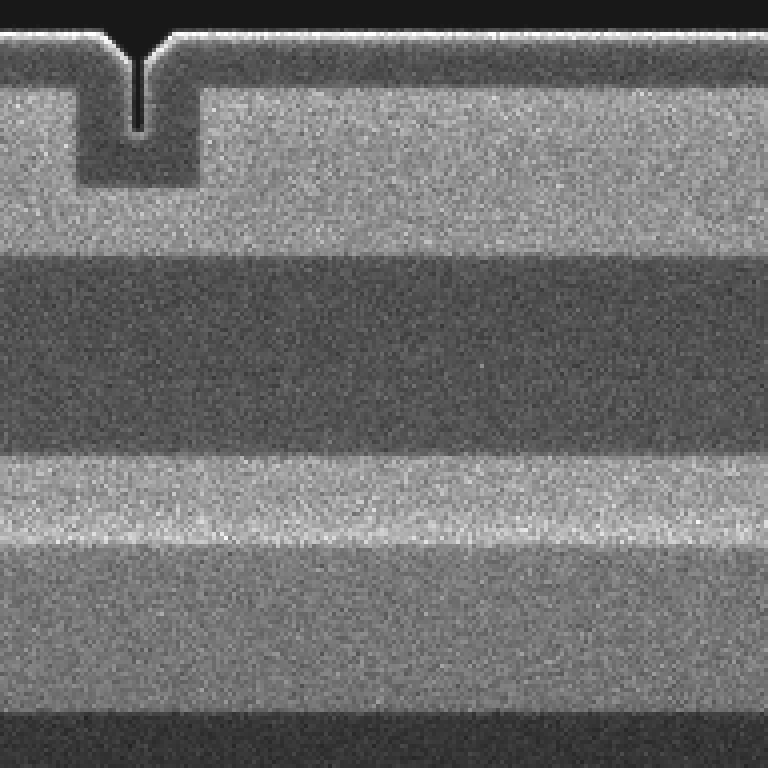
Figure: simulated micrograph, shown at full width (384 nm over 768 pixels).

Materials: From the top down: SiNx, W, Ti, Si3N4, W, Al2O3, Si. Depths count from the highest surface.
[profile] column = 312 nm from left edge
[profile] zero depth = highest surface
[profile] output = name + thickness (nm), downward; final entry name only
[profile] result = SiNx 28, W 84, Ti 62, Si3N4 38, W 44, Al2O3 84, Si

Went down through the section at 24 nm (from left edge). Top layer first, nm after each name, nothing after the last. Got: SiNx 28, W 84, Ti 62, Si3N4 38, W 44, Al2O3 84, Si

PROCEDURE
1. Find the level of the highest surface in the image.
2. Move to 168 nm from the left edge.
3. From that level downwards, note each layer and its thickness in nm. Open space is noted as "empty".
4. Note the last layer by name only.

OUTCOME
SiNx 28, W 84, Ti 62, Si3N4 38, W 44, Al2O3 84, Si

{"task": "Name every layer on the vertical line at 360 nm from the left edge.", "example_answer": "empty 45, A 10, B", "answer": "SiNx 28, W 84, Ti 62, Si3N4 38, W 44, Al2O3 84, Si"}